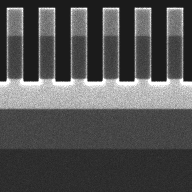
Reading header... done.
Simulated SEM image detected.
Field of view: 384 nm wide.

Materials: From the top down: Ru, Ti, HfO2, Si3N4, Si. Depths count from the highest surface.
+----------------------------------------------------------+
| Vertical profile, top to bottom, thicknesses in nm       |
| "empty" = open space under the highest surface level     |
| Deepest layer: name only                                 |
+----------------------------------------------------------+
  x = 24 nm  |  Ru 56, Ti 86, HfO2 60, Si3N4 80, Si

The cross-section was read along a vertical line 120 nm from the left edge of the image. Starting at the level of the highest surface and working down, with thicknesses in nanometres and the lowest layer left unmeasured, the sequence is empty 148, HfO2 54, Si3N4 80, Si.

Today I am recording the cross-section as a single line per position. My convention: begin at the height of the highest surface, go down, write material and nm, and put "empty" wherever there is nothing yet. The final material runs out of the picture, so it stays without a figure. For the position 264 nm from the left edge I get empty 148, HfO2 54, Si3N4 80, Si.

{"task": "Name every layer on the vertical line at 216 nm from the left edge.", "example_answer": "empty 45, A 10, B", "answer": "Ru 56, Ti 86, HfO2 60, Si3N4 80, Si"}